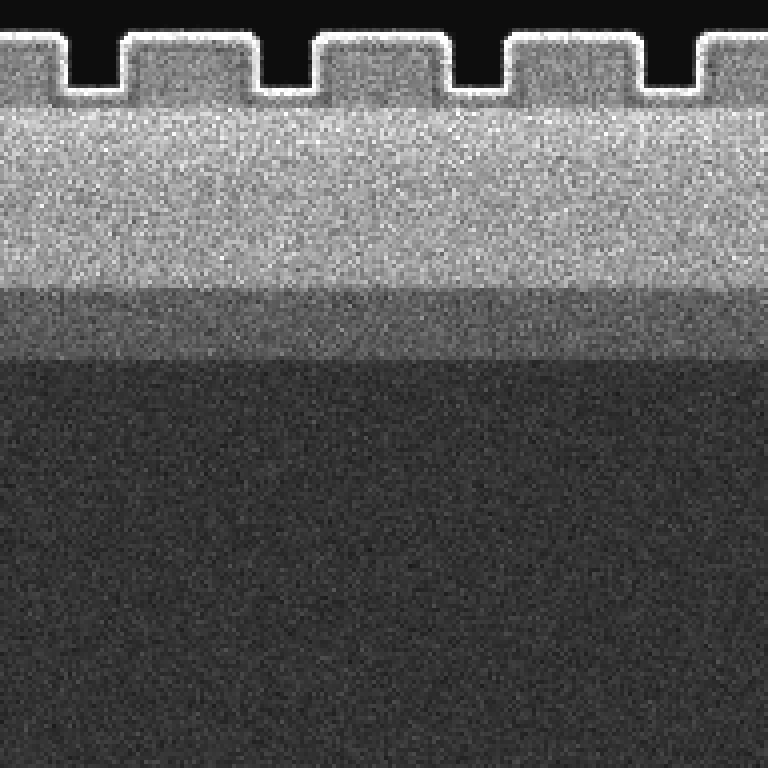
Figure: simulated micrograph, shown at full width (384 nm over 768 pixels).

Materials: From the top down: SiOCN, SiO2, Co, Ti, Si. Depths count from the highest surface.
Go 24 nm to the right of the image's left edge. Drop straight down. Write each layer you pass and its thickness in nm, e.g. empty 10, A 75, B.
SiOCN 38, Co 90, Ti 36, Si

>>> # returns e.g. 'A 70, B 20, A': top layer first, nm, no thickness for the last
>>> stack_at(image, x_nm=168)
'SiOCN 10, SiO2 28, Co 90, Ti 36, Si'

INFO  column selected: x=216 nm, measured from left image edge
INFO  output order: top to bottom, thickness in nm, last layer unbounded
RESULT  SiOCN 38, Co 90, Ti 36, Si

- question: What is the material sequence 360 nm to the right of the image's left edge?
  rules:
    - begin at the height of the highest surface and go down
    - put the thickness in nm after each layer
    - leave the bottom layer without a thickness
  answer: SiOCN 10, SiO2 28, Co 90, Ti 36, Si